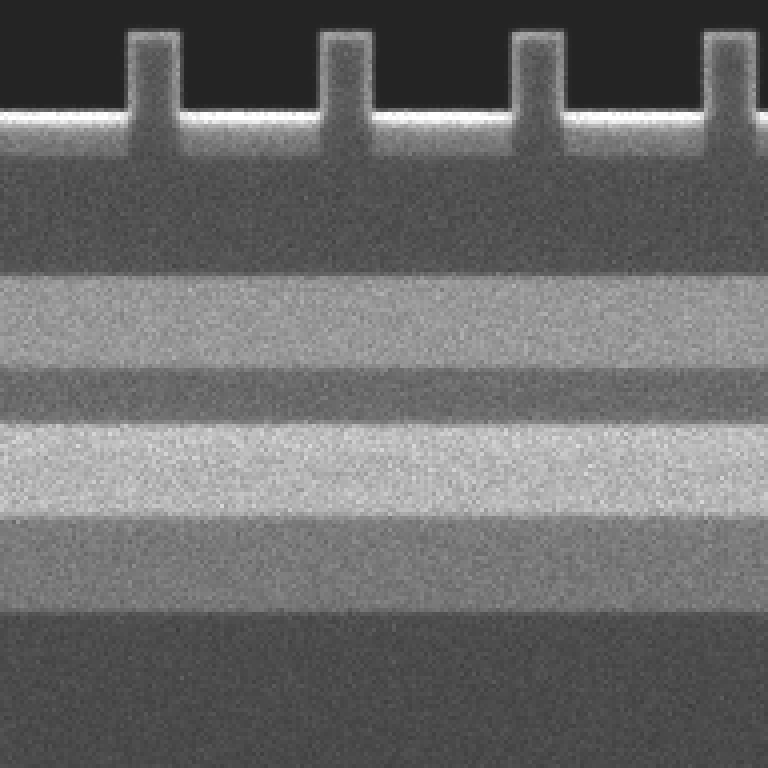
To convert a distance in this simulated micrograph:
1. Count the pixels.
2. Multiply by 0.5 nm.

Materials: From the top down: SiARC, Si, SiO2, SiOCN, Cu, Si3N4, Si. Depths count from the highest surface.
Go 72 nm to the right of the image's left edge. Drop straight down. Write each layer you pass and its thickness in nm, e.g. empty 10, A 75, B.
Si 122, SiO2 46, SiOCN 28, Cu 46, Si3N4 48, Si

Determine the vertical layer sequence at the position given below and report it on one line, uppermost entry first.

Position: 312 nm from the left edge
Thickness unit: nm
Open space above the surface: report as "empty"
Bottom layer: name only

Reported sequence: empty 40, SiARC 22, Si 60, SiO2 46, SiOCN 28, Cu 46, Si3N4 48, Si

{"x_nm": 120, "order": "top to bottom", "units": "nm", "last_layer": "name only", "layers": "empty 40, SiARC 22, Si 60, SiO2 46, SiOCN 28, Cu 46, Si3N4 48, Si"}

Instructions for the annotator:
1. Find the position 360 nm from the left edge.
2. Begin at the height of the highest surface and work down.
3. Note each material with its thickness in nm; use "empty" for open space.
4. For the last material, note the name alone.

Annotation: Si 122, SiO2 46, SiOCN 28, Cu 46, Si3N4 48, Si